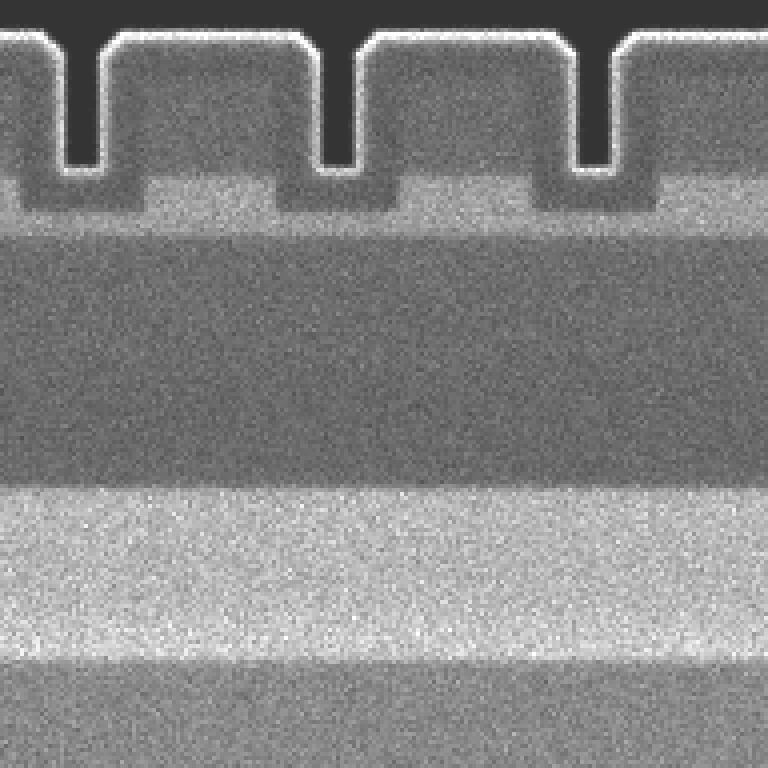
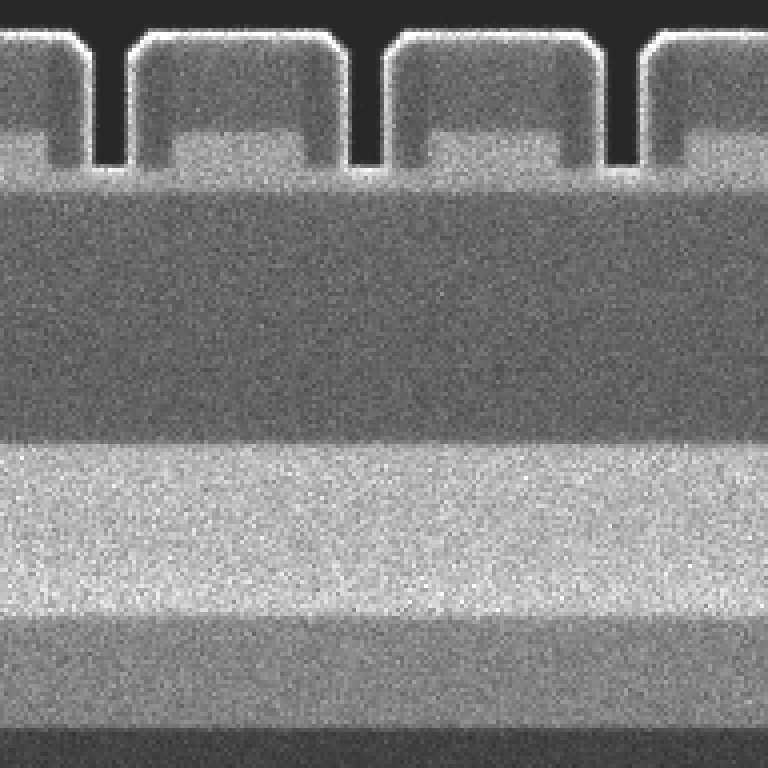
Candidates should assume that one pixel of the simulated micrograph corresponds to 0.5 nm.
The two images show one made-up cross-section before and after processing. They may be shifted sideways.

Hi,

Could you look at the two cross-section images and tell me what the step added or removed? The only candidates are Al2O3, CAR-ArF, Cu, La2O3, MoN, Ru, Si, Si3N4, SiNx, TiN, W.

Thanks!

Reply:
removed SiNx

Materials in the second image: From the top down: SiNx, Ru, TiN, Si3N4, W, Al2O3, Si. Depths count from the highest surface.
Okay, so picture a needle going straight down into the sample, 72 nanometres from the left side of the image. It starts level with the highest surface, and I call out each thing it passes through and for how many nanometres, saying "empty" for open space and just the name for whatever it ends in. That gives empty 2, SiNx 66, Ru 12, TiN 66, Si3N4 60, W 86, Al2O3 56, Si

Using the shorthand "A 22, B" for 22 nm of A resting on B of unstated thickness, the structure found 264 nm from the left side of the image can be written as TiN 50, Ru 30, TiN 66, Si3N4 60, W 86, Al2O3 56, Si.